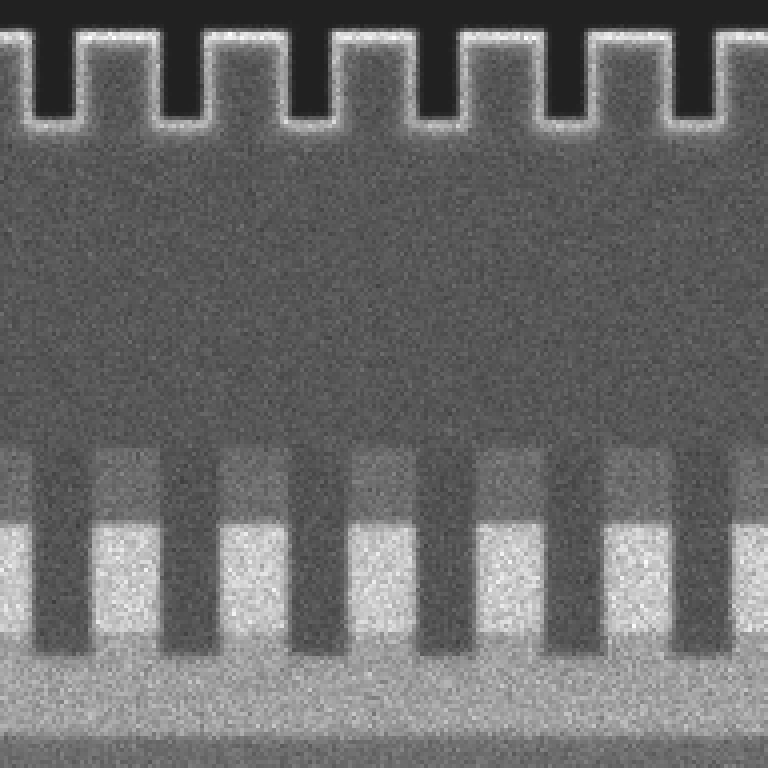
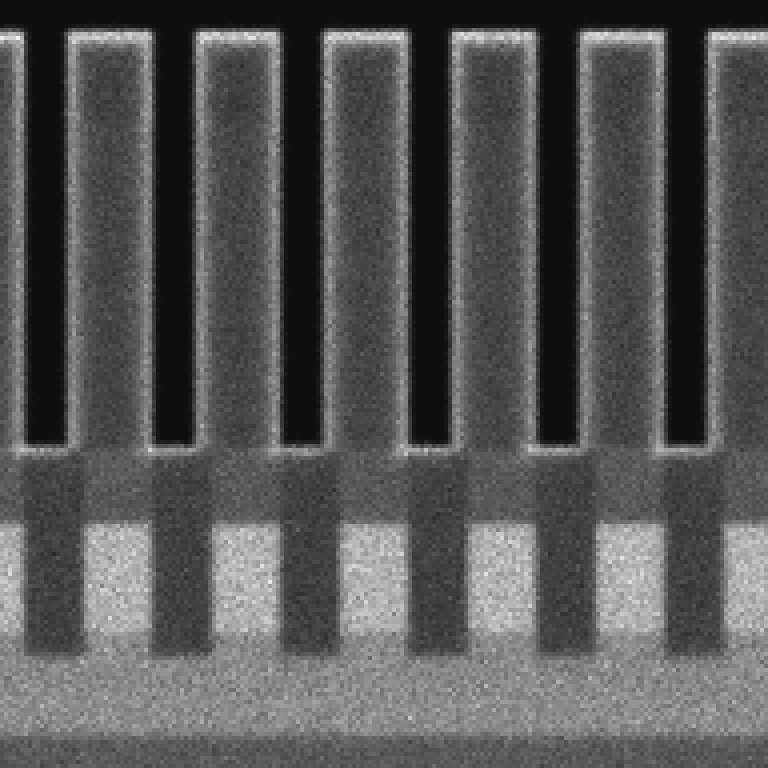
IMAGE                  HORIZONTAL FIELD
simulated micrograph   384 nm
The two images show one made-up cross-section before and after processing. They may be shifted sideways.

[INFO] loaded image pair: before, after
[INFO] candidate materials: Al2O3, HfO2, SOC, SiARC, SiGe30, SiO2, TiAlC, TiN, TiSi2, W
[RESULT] removed SOC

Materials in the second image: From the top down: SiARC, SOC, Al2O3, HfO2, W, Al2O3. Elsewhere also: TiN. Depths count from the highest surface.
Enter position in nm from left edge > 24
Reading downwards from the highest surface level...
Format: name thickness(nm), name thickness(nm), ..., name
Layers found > empty 208, TiN 104, W 40, Al2O3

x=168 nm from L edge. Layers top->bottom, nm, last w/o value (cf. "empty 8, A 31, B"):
SiARC 44, SOC 164, TiN 104, W 40, Al2O3